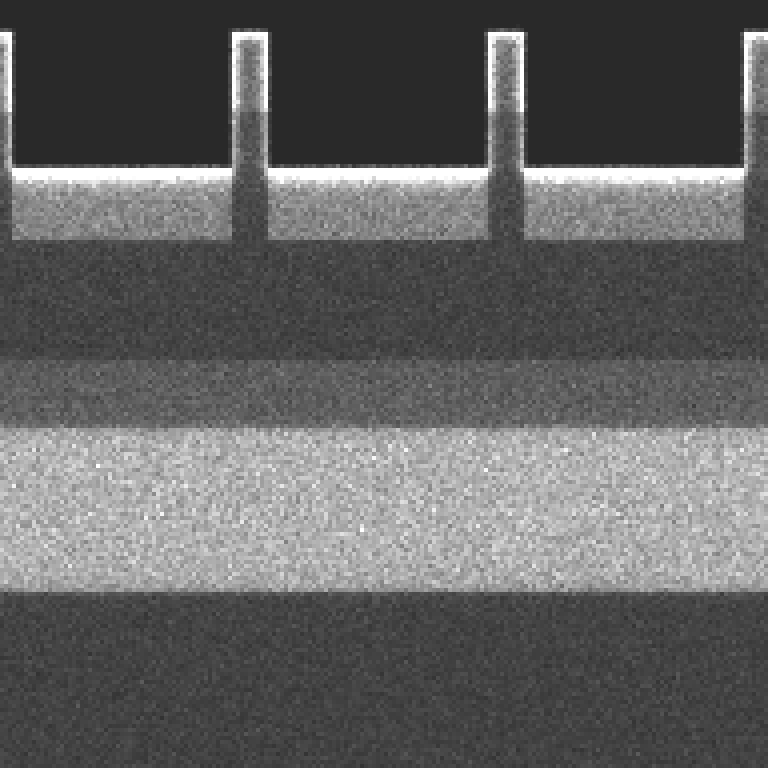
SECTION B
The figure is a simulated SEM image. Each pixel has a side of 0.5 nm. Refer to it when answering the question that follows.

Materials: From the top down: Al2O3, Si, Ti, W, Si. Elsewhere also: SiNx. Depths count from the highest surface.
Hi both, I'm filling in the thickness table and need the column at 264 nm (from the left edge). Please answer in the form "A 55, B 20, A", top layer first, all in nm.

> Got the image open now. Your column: empty 68, Al2O3 36, Si 60, Ti 34, W 82, Si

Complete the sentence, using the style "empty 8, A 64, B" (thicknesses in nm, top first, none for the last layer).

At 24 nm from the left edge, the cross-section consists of empty 68, Al2O3 36, Si 60, Ti 34, W 82, Si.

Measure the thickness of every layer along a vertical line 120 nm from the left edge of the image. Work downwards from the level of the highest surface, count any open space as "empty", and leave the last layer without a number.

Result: SiNx 40, Si 124, Ti 34, W 82, Si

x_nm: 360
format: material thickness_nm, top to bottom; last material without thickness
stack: empty 68, Al2O3 36, Si 60, Ti 34, W 82, Si